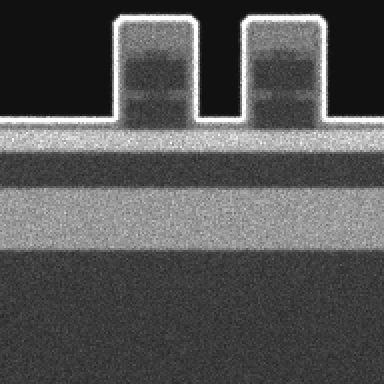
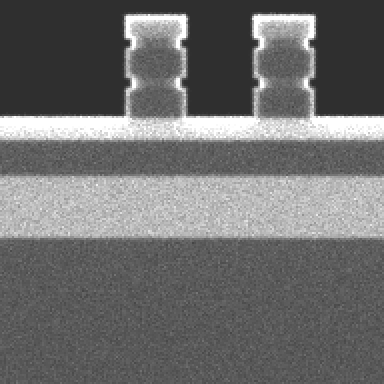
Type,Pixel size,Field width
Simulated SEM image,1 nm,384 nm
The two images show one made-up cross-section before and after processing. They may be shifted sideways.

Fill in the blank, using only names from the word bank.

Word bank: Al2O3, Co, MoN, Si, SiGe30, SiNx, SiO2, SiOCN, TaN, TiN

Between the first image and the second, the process removed SiNx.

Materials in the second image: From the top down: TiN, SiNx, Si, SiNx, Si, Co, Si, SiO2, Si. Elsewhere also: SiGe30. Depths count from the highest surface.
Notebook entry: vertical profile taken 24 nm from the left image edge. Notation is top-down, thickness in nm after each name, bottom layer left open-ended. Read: empty 102, Co 22, Si 36, SiO2 62, Si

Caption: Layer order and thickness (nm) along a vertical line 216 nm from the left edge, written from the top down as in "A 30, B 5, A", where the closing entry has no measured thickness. empty 102, Co 22, Si 36, SiO2 62, Si